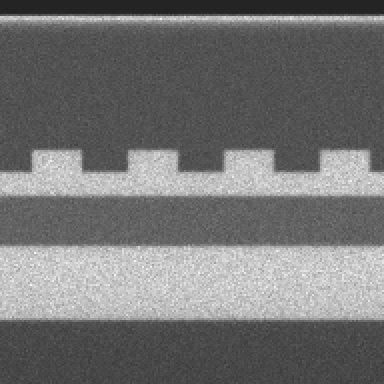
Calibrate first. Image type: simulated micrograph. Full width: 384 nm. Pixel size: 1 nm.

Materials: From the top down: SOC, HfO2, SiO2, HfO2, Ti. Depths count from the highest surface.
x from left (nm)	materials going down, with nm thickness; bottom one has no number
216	SOC 156, HfO2 24, SiO2 50, HfO2 74, Ti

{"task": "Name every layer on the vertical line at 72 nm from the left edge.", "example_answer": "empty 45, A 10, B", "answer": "SOC 134, HfO2 46, SiO2 50, HfO2 74, Ti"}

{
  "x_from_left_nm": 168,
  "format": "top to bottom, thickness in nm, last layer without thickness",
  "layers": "SOC 134, HfO2 46, SiO2 50, HfO2 74, Ti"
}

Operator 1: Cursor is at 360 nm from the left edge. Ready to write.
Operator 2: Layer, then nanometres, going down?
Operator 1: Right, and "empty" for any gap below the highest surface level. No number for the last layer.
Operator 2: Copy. SOC 134, HfO2 46, SiO2 50, HfO2 74, Ti